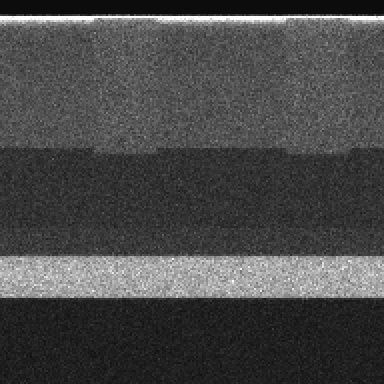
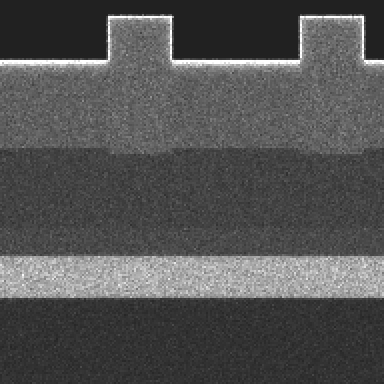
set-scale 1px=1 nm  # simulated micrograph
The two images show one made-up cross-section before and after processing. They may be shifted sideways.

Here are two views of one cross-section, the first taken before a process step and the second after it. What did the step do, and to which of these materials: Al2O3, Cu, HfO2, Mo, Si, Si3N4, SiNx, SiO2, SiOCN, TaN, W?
It removed SiO2.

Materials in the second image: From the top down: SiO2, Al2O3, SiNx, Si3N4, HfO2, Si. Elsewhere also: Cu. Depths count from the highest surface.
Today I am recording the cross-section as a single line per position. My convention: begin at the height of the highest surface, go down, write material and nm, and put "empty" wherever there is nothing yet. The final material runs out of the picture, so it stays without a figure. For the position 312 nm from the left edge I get Cu 138, SiNx 74, Si3N4 28, HfO2 42, Si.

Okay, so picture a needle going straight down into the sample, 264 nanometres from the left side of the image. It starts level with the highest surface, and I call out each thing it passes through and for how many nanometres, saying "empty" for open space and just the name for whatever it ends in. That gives empty 44, SiO2 10, Al2O3 78, SiNx 80, Si3N4 28, HfO2 42, Si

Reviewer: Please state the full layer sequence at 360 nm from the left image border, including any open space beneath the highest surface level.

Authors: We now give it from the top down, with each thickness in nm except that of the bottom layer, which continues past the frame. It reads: Cu 138, SiNx 74, Si3N4 28, HfO2 42, Si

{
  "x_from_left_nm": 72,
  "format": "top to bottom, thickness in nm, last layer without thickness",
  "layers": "empty 44, SiO2 10, Al2O3 78, SiNx 80, Si3N4 28, HfO2 42, Si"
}